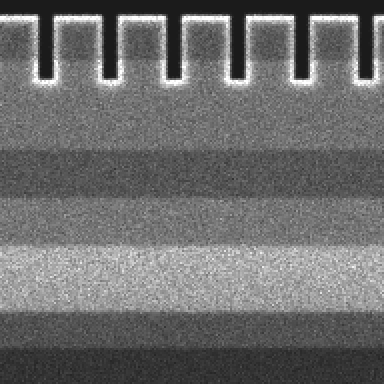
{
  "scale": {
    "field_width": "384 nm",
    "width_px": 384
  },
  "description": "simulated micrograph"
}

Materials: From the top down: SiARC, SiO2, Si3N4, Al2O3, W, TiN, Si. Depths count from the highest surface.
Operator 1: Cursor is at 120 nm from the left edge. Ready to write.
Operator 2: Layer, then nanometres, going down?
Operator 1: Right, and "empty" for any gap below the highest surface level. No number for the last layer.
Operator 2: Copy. SiARC 44, SiO2 90, Si3N4 48, Al2O3 48, W 66, TiN 36, Si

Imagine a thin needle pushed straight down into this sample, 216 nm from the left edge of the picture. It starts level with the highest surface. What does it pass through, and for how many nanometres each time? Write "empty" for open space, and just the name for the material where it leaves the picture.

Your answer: SiARC 44, SiO2 90, Si3N4 48, Al2O3 48, W 66, TiN 36, Si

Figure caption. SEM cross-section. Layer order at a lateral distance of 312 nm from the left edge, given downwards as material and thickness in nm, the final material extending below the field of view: SiARC 44, SiO2 90, Si3N4 48, Al2O3 48, W 66, TiN 36, Si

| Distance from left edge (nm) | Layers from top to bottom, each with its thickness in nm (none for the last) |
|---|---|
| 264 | SiARC 44, SiO2 90, Si3N4 48, Al2O3 48, W 66, TiN 36, Si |